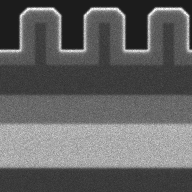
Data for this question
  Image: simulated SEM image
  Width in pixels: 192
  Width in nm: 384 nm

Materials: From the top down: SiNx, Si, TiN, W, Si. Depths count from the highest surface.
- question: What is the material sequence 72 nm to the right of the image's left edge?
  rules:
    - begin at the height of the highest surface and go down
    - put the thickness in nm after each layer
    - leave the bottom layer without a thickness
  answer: SiNx 30, Si 144, TiN 58, W 88, Si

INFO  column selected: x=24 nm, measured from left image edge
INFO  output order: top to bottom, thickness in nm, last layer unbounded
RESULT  empty 84, SiNx 30, Si 60, TiN 58, W 88, Si